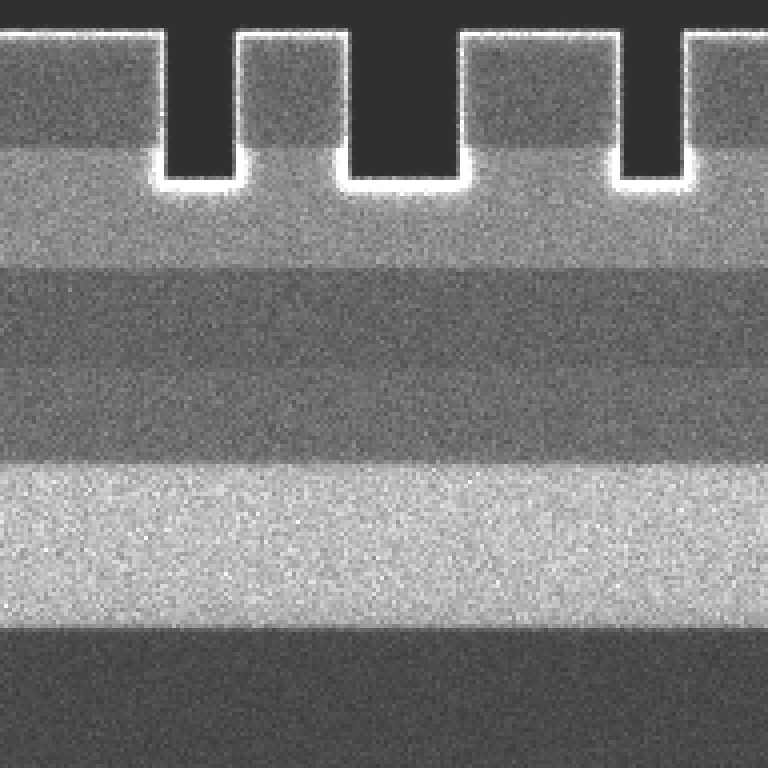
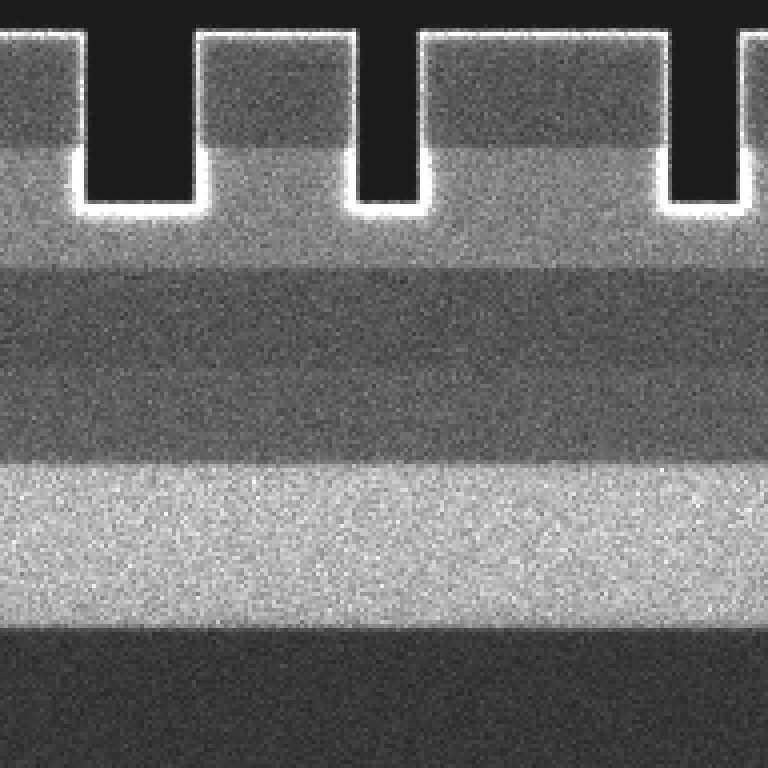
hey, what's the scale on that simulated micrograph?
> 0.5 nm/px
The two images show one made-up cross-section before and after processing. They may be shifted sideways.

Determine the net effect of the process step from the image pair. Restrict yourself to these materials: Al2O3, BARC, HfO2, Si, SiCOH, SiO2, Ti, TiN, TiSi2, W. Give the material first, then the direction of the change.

Al2O3: removed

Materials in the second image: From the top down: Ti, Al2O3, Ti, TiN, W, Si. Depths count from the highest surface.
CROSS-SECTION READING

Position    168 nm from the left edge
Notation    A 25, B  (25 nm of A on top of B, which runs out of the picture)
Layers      Ti 58, Al2O3 60, Ti 50, TiN 48, W 82, Si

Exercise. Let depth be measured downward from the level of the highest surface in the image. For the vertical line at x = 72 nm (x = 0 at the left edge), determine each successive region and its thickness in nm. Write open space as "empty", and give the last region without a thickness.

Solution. empty 86, Al2O3 32, Ti 50, TiN 48, W 82, Si